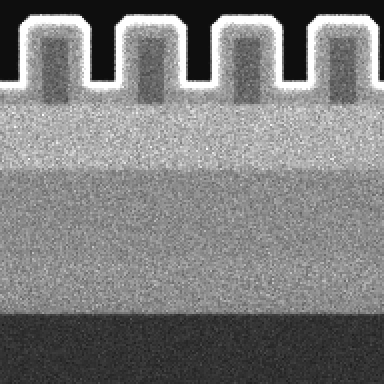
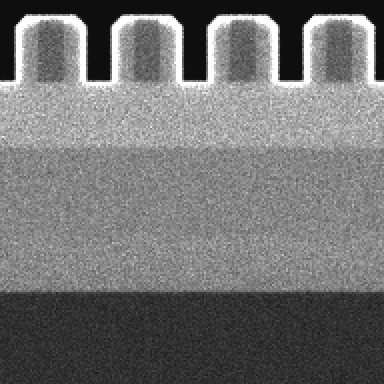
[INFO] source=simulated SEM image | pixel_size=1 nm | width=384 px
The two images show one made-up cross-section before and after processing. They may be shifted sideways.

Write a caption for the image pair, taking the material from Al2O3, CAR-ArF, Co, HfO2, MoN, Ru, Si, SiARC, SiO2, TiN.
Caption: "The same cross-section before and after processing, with Al2O3 removed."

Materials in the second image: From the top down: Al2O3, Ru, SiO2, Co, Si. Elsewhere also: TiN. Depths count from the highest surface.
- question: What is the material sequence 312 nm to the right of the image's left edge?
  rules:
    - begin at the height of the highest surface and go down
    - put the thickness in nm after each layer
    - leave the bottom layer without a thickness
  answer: empty 2, Al2O3 64, Ru 66, SiO2 88, Co 56, Si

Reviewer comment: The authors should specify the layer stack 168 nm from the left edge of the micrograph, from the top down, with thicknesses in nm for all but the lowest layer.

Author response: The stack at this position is Al2O3 66, Ru 66, SiO2 88, Co 56, Si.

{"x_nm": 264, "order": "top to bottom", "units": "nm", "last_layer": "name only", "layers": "Al2O3 66, Ru 66, SiO2 88, Co 56, Si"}